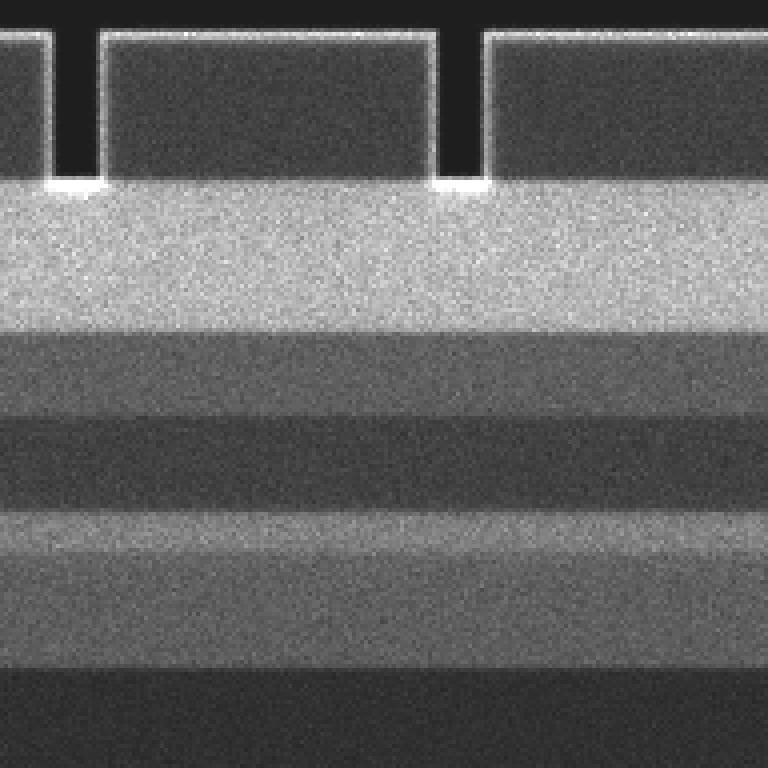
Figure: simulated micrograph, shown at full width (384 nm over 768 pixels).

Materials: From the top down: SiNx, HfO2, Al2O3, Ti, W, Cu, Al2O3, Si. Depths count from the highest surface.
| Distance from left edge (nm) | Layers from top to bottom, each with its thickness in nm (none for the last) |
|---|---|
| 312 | SiNx 74, HfO2 76, Al2O3 42, Ti 48, W 20, Cu 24, Al2O3 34, Si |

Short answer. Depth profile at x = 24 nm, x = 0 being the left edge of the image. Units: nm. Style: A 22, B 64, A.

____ SiNx 74, HfO2 76, Al2O3 42, Ti 48, W 20, Cu 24, Al2O3 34, Si